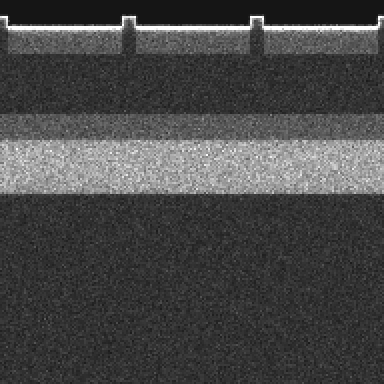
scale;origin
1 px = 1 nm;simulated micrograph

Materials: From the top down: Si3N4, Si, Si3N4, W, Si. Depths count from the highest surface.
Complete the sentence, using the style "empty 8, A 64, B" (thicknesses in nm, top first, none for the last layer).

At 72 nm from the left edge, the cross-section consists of empty 10, Si3N4 28, Si 60, Si3N4 26, W 54, Si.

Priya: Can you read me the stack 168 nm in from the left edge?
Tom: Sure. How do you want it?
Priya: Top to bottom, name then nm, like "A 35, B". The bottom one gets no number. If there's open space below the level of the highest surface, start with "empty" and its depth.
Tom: empty 10, Si3N4 28, Si 60, Si3N4 26, W 54, Si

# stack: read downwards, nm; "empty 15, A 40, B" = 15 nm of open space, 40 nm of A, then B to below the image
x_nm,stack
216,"empty 10, Si3N4 28, Si 60, Si3N4 26, W 54, Si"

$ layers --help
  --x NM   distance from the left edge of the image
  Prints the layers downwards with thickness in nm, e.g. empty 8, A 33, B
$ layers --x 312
empty 10, Si3N4 28, Si 60, Si3N4 26, W 54, Si